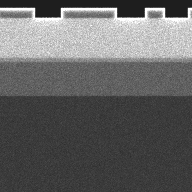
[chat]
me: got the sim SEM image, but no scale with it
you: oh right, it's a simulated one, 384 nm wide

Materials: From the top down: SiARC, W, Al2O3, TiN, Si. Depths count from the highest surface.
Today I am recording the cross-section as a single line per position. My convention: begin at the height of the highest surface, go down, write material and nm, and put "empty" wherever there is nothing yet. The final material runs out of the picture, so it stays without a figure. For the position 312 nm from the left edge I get SiARC 20, W 80, Al2O3 8, TiN 68, Si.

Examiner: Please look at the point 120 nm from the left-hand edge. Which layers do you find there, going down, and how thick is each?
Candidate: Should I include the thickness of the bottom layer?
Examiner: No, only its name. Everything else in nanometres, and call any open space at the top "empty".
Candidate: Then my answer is empty 20, W 80, Al2O3 8, TiN 68, Si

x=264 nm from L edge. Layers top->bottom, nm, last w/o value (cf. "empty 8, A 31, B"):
empty 20, W 80, Al2O3 8, TiN 68, Si